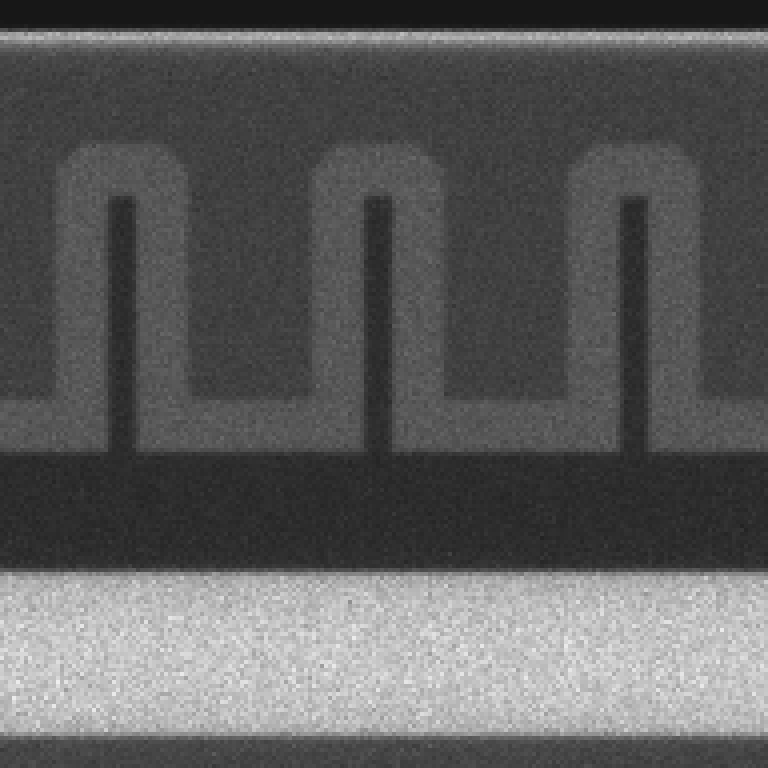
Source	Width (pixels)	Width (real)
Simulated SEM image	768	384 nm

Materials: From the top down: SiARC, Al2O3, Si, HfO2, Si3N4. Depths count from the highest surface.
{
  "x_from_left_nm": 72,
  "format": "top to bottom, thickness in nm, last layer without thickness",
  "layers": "SiARC 56, Al2O3 154, Si 60, HfO2 82, Si3N4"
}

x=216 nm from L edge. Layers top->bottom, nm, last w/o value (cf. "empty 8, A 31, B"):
SiARC 64, Al2O3 146, Si 60, HfO2 82, Si3N4